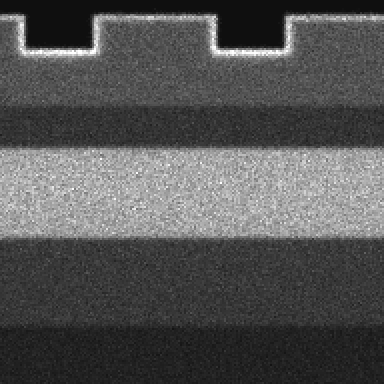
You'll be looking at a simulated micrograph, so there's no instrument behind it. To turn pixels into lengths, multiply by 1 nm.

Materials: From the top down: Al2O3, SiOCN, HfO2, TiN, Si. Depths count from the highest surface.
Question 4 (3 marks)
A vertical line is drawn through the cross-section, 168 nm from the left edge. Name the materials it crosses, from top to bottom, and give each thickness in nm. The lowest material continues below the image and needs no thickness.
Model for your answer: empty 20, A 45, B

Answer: Al2O3 90, SiOCN 42, HfO2 90, TiN 88, Si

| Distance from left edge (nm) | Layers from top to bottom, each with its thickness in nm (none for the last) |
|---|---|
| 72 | empty 34, Al2O3 56, SiOCN 42, HfO2 90, TiN 88, Si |